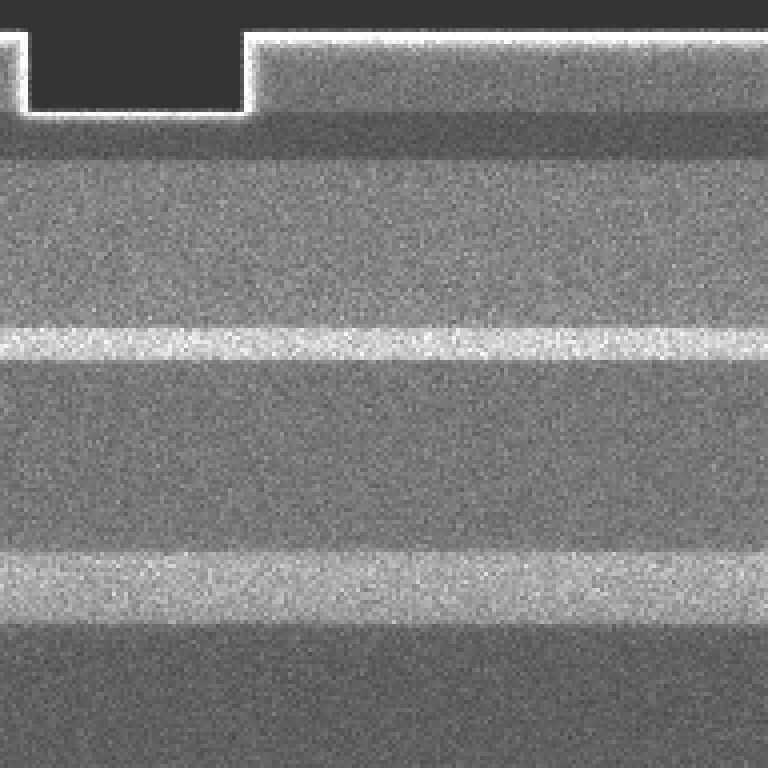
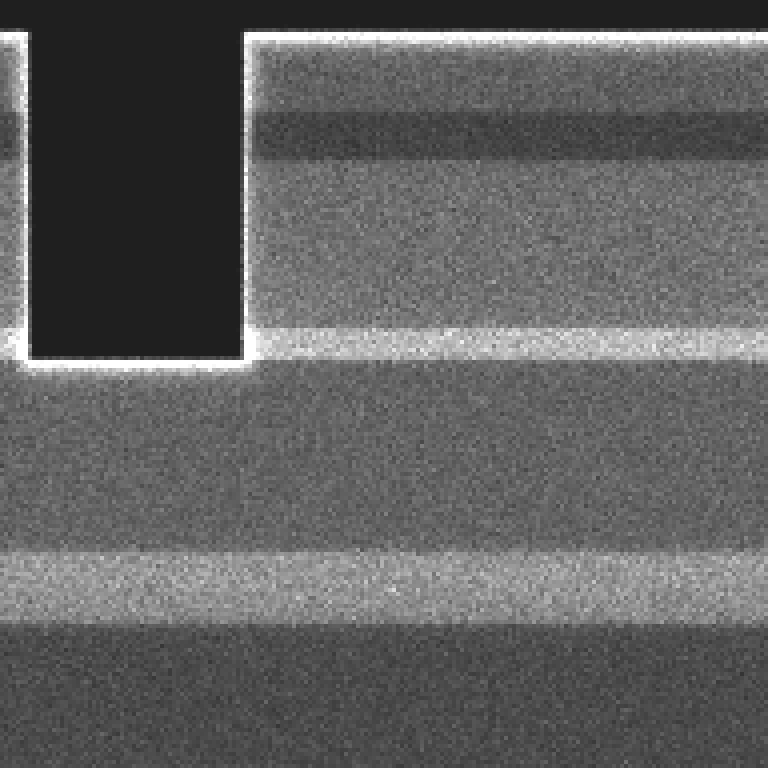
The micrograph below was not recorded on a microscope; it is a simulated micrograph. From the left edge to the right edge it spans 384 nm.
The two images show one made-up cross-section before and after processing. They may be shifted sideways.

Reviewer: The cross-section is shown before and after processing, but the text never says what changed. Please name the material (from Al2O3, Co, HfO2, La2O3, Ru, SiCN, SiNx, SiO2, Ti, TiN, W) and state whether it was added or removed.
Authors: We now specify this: Co and HfO2 and SiNx, removed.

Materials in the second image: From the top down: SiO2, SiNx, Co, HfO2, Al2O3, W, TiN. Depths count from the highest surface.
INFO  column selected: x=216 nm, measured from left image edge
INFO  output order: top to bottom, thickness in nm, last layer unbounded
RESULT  SiO2 40, SiNx 24, Co 84, HfO2 16, Al2O3 96, W 36, TiN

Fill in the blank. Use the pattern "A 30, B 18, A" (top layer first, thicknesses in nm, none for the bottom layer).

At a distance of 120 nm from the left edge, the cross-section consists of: empty 164, Al2O3 96, W 36, TiN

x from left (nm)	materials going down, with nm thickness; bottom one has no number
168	SiO2 40, SiNx 24, Co 84, HfO2 16, Al2O3 96, W 36, TiN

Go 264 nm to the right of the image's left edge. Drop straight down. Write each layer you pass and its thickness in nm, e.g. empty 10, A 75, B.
SiO2 40, SiNx 24, Co 84, HfO2 16, Al2O3 96, W 36, TiN